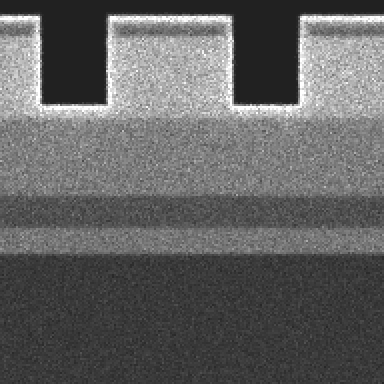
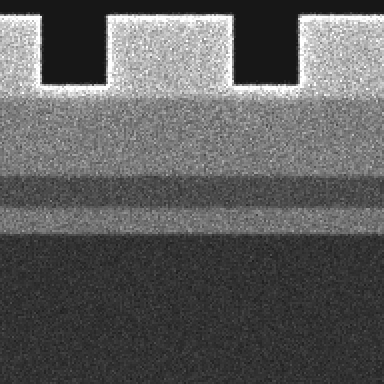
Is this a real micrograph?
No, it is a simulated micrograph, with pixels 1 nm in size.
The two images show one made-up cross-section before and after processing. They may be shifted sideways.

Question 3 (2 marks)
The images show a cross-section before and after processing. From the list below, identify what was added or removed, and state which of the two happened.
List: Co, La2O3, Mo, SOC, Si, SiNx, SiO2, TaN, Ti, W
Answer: SOC was removed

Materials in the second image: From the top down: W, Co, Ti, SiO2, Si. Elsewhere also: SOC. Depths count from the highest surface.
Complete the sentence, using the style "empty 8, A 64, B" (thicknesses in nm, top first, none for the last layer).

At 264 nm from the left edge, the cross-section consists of empty 70, W 12, Co 78, Ti 32, SiO2 26, Si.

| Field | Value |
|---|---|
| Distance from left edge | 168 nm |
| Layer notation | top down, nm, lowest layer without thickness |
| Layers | W 82, Co 78, Ti 32, SiO2 26, Si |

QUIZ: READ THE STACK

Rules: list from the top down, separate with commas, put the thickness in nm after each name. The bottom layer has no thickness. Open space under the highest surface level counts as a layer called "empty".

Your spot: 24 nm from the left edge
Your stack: W 82, Co 78, Ti 32, SiO2 26, Si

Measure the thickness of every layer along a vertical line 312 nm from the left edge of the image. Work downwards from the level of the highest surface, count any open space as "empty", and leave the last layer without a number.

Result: W 82, Co 78, Ti 32, SiO2 26, Si